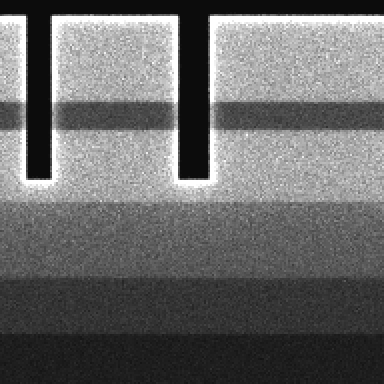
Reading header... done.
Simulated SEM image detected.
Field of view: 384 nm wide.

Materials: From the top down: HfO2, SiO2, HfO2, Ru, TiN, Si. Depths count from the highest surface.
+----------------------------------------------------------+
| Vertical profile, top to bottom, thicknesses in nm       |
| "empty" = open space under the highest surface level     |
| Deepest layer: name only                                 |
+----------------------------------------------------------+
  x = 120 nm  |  HfO2 86, SiO2 28, HfO2 72, Ru 76, TiN 56, Si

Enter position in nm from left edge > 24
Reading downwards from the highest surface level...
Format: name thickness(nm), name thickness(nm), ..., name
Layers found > HfO2 86, SiO2 28, HfO2 72, Ru 76, TiN 56, Si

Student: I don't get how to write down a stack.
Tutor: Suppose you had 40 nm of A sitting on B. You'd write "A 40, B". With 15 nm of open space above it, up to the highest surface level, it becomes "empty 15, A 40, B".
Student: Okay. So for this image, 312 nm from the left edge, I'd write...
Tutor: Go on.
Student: HfO2 86, SiO2 28, HfO2 72, Ru 76, TiN 56, Si